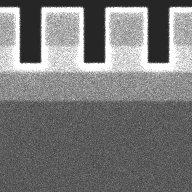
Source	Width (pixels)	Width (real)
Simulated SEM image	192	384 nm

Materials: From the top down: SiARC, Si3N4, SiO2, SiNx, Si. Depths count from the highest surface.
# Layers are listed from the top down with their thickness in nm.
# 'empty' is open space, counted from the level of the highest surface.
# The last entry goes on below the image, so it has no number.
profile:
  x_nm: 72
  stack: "empty 112, SiO2 16, SiNx 58, Si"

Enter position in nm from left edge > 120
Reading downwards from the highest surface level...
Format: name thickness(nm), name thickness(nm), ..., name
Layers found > SiARC 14, Si3N4 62, SiO2 52, SiNx 58, Si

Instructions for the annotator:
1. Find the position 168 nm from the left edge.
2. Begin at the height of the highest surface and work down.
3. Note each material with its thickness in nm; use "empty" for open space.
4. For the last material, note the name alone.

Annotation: empty 112, SiO2 16, SiNx 58, Si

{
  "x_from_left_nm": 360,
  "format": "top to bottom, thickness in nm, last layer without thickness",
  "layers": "SiARC 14, Si3N4 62, SiO2 52, SiNx 58, Si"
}